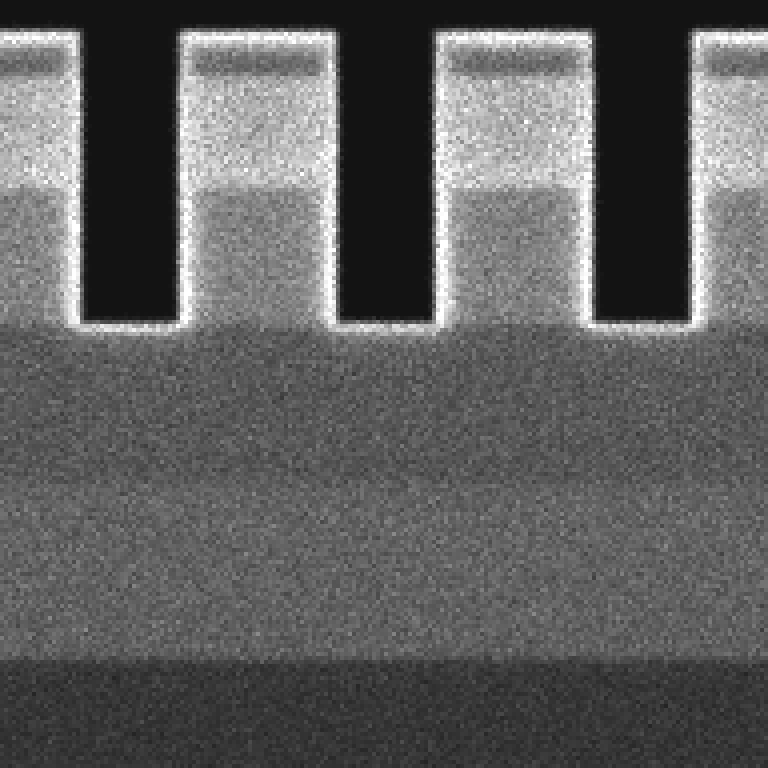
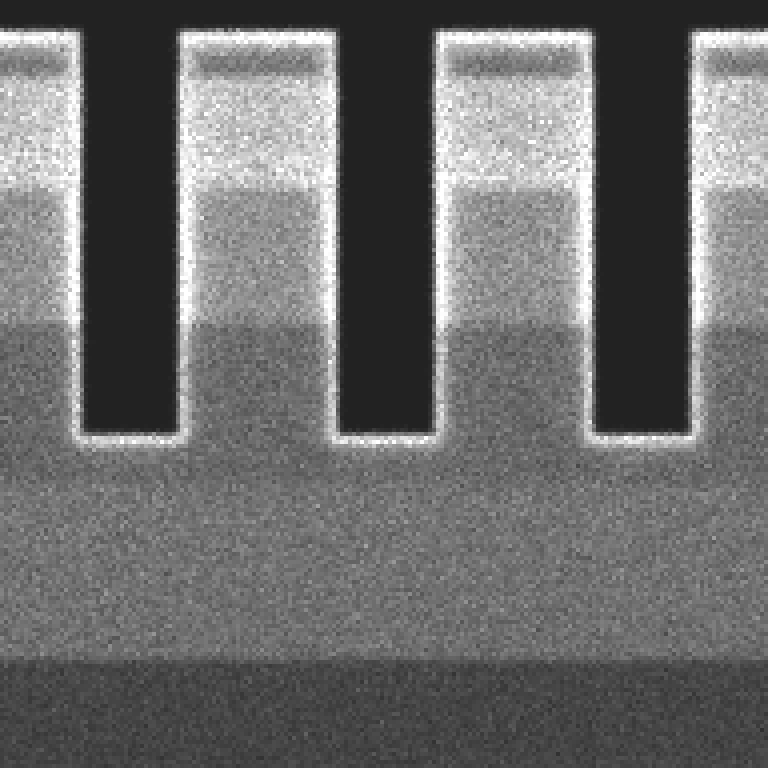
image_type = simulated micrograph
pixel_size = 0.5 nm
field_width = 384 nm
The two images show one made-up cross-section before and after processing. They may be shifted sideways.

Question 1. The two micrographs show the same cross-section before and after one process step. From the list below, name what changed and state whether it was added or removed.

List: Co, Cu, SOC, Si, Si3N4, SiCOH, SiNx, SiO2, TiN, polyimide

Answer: SiNx, removed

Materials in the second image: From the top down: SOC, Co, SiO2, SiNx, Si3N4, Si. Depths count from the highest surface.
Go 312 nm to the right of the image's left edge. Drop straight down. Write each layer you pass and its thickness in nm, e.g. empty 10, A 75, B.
empty 202, SiNx 24, Si3N4 88, Si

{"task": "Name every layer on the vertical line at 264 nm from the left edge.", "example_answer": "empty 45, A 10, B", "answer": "SOC 22, Co 56, SiO2 68, SiNx 80, Si3N4 88, Si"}